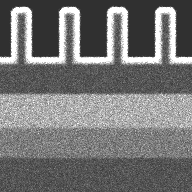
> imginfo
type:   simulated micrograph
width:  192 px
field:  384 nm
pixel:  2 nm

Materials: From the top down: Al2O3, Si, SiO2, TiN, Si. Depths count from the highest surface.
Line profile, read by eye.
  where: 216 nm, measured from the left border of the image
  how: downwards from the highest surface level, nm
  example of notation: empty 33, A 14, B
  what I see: empty 6, Al2O3 106, Si 60, SiO2 68, TiN 60, Si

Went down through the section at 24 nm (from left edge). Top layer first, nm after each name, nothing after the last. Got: empty 6, Al2O3 106, Si 60, SiO2 68, TiN 60, Si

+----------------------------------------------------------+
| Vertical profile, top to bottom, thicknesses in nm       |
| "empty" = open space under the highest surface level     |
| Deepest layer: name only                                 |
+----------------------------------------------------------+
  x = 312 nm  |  empty 6, Al2O3 106, Si 60, SiO2 68, TiN 60, Si